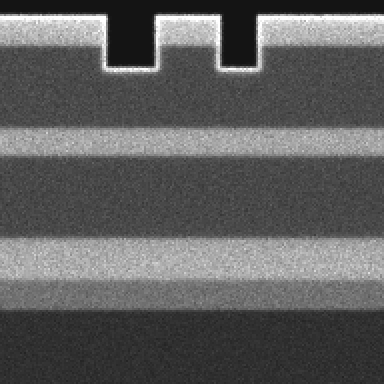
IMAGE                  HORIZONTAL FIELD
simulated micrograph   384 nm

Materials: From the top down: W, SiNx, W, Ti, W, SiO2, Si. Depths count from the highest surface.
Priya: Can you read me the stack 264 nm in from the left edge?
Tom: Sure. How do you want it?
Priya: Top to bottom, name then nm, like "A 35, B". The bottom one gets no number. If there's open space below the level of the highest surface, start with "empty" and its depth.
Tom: W 30, SiNx 82, W 28, Ti 82, W 42, SiO2 30, Si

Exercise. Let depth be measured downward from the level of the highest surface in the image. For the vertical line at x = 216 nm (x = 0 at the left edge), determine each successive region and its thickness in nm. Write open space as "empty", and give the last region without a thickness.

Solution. W 30, SiNx 82, W 28, Ti 82, W 42, SiO2 30, Si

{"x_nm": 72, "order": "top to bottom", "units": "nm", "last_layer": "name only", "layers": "W 30, SiNx 82, W 28, Ti 82, W 42, SiO2 30, Si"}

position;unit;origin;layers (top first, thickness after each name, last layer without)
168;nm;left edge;W 30, SiNx 82, W 28, Ti 82, W 42, SiO2 30, Si